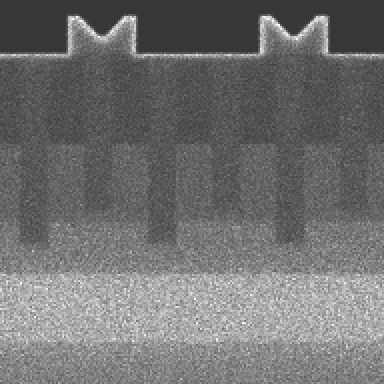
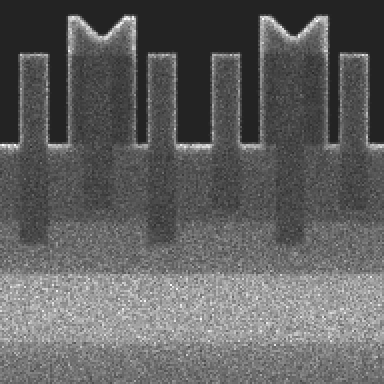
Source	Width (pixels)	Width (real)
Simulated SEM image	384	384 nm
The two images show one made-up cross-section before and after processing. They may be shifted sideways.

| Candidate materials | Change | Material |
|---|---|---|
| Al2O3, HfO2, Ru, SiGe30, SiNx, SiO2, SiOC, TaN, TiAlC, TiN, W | removed | SiNx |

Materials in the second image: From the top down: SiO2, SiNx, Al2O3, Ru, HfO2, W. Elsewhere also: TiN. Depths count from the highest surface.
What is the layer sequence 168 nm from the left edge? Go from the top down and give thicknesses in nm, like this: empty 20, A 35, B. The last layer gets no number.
empty 38, TiN 190, Ru 30, HfO2 68, W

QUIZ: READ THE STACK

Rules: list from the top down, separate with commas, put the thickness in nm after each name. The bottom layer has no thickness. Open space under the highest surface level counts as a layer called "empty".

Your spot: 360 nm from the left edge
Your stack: empty 38, TiN 156, Al2O3 12, Ru 52, HfO2 68, W